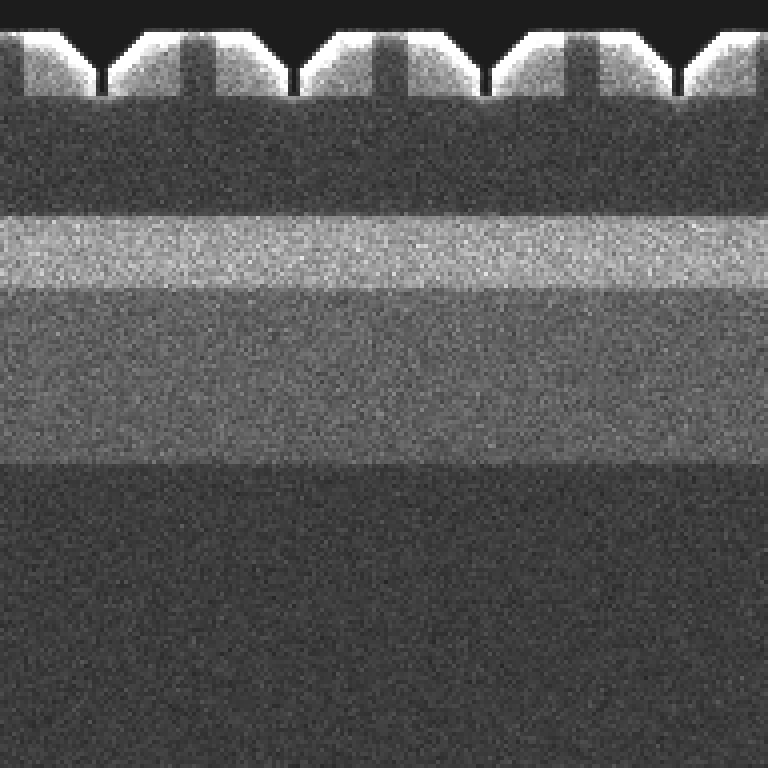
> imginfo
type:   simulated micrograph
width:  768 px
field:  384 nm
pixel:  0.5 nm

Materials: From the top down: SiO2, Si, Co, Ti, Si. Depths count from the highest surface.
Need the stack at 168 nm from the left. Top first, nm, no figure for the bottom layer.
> SiO2 32, Si 60, Co 36, Ti 88, Si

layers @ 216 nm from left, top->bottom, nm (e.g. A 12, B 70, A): SiO2 32, Si 60, Co 36, Ti 88, Si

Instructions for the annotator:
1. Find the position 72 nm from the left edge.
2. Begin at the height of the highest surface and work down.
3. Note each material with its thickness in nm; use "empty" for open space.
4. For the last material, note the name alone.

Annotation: SiO2 32, Si 60, Co 36, Ti 88, Si